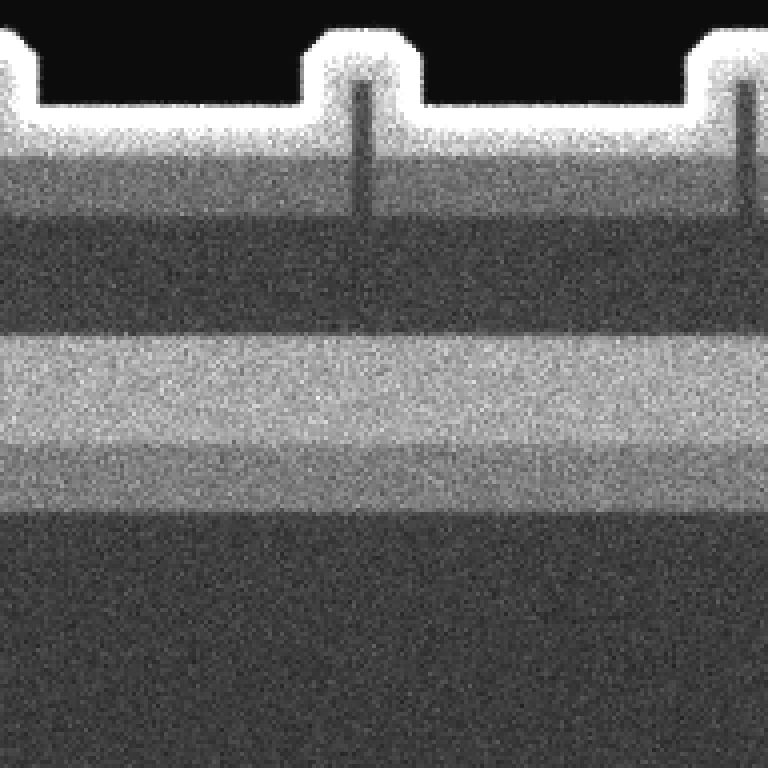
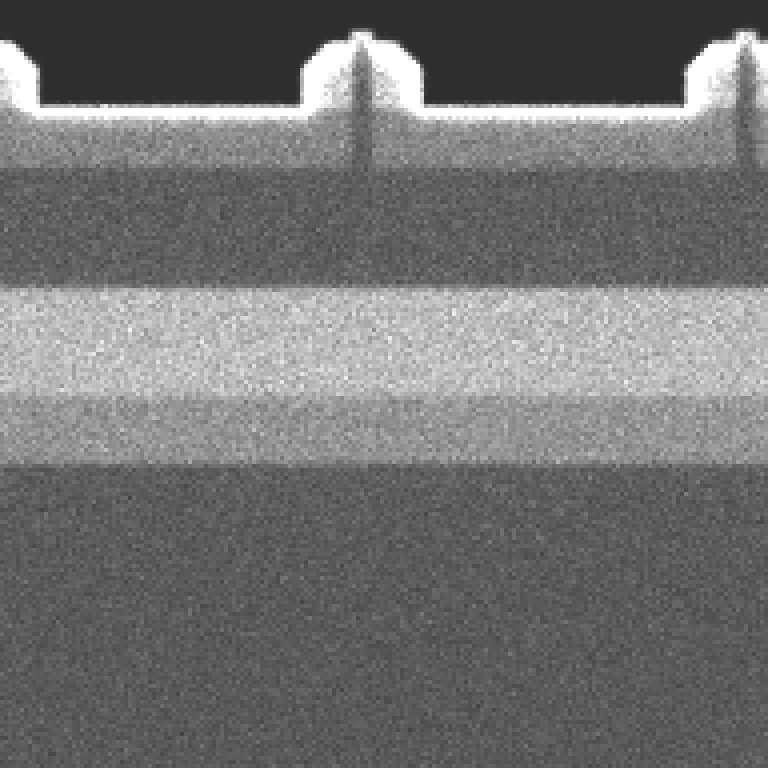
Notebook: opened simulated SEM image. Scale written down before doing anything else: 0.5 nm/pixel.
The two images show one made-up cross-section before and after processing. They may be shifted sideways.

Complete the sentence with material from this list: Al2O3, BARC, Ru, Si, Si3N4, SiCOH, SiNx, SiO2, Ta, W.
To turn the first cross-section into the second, Al2O3 must be removed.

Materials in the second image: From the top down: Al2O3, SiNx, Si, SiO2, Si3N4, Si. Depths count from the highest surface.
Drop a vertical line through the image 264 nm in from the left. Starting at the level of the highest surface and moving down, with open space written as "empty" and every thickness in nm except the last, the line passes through empty 38, SiNx 30, Si 60, SiO2 54, Si3N4 34, Si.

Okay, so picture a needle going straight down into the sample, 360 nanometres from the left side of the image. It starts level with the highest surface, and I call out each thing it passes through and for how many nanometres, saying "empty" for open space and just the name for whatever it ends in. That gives empty 6, Al2O3 32, SiNx 30, Si 60, SiO2 54, Si3N4 34, Si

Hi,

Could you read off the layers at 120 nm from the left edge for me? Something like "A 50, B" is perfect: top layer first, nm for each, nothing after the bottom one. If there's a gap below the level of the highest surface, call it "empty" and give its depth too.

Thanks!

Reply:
empty 38, SiNx 30, Si 60, SiO2 54, Si3N4 34, Si